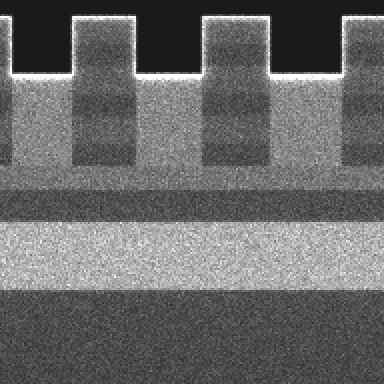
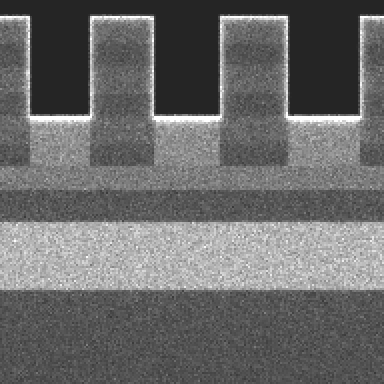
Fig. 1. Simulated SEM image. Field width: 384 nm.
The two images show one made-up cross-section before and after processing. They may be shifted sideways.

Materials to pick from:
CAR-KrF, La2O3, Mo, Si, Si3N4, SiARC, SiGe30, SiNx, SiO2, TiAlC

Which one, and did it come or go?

Si3N4 - removed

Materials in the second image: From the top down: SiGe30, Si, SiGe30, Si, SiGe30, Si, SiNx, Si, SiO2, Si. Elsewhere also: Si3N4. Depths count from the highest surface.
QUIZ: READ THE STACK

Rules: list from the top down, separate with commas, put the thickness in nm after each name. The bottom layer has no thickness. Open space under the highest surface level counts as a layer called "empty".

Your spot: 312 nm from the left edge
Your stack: empty 100, Si3N4 50, SiNx 24, Si 32, SiO2 68, Si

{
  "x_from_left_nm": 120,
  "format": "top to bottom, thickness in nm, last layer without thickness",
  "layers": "SiGe30 28, Si 22, SiGe30 28, Si 22, SiGe30 28, Si 22, SiNx 24, Si 32, SiO2 68, Si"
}